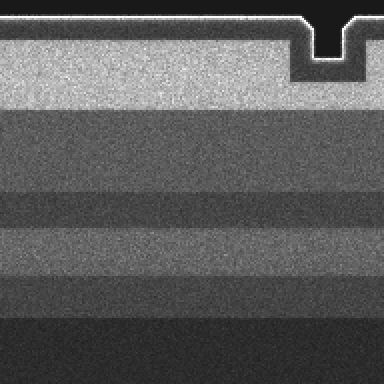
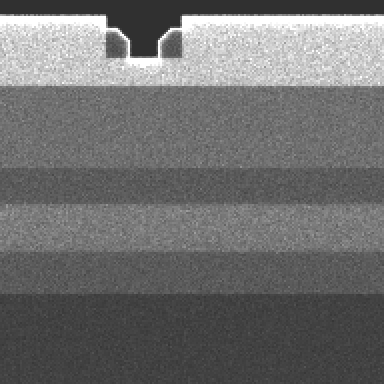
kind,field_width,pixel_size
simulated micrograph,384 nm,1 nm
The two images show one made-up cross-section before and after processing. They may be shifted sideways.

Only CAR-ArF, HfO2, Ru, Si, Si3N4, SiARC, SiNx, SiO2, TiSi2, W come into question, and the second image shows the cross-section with SiNx removed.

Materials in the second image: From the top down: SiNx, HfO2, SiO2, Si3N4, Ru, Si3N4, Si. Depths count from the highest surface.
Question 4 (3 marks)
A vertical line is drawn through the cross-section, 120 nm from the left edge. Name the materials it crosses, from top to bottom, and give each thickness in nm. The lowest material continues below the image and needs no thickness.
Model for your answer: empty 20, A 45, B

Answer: empty 16, SiNx 26, HfO2 28, SiO2 82, Si3N4 36, Ru 48, Si3N4 42, Si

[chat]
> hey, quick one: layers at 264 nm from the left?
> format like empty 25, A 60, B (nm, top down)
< HfO2 70, SiO2 82, Si3N4 36, Ru 48, Si3N4 42, Si